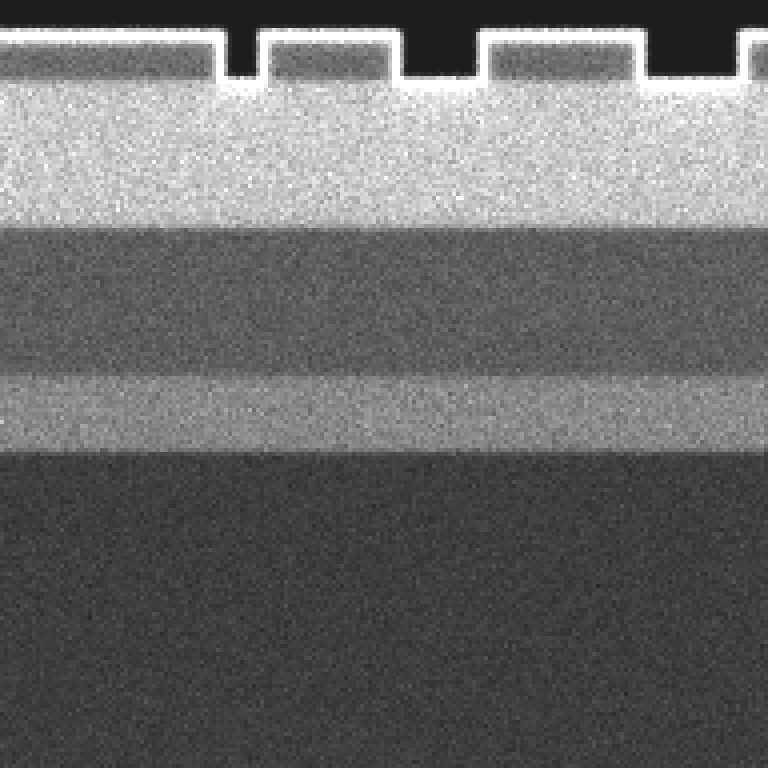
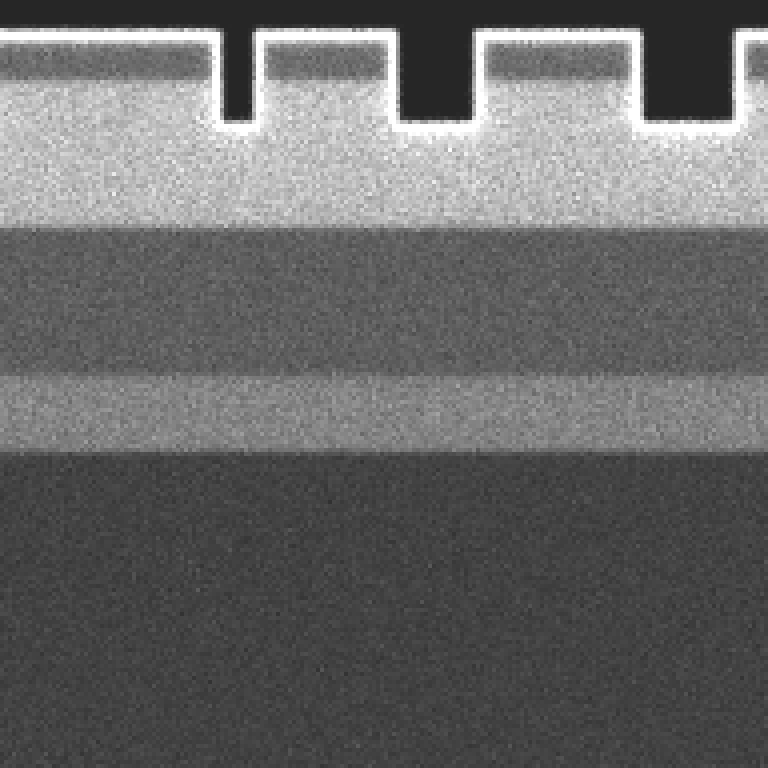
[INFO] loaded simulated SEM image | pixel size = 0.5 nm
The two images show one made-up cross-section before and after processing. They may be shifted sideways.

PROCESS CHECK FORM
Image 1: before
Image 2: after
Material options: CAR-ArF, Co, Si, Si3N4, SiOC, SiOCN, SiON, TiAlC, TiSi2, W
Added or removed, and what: removed, W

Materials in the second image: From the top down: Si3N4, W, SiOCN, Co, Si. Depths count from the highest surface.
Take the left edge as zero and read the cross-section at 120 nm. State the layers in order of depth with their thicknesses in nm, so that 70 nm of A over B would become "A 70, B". empty 46, W 52, SiOCN 74, Co 38, Si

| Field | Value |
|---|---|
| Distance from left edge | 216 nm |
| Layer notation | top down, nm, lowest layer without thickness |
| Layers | empty 46, W 52, SiOCN 74, Co 38, Si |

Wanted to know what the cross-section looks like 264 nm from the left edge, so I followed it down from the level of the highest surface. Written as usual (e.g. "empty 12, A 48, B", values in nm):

Si3N4 24, W 74, SiOCN 74, Co 38, Si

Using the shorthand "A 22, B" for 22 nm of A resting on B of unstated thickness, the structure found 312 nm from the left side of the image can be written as Si3N4 24, W 74, SiOCN 74, Co 38, Si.